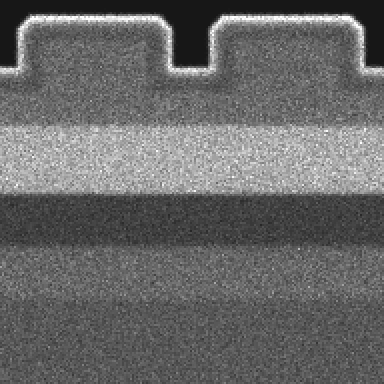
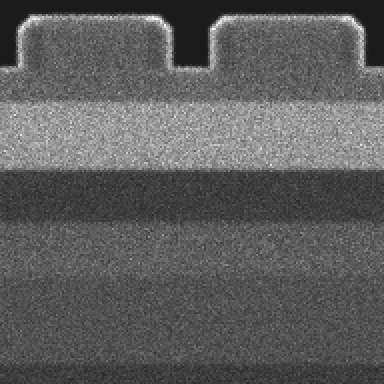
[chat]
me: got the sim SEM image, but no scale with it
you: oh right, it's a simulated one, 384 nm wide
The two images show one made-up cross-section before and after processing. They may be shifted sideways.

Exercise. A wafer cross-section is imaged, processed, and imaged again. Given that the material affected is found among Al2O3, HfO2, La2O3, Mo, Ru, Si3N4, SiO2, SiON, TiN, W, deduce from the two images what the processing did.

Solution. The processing removed SiO2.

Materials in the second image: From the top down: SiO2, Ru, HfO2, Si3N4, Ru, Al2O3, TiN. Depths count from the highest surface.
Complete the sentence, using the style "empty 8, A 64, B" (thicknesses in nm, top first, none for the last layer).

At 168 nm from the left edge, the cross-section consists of empty 10, SiO2 42, Ru 34, HfO2 68, Si3N4 52, Ru 54, Al2O3 88, TiN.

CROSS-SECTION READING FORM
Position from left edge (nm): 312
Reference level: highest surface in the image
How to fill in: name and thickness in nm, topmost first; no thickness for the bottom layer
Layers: Ru 86, HfO2 68, Si3N4 52, Ru 54, Al2O3 88, TiN